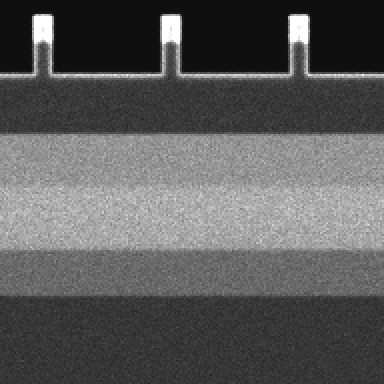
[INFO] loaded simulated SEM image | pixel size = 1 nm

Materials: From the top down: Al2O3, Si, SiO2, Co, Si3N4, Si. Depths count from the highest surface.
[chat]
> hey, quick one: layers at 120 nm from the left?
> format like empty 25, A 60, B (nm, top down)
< empty 58, Si 60, SiO2 52, Co 64, Si3N4 46, Si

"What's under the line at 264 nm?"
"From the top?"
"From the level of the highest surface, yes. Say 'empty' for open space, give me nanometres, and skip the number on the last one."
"empty 58, Si 60, SiO2 52, Co 64, Si3N4 46, Si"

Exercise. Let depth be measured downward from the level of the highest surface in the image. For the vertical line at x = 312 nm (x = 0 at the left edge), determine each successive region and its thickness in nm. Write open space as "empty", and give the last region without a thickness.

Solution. empty 58, Si 60, SiO2 52, Co 64, Si3N4 46, Si